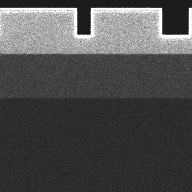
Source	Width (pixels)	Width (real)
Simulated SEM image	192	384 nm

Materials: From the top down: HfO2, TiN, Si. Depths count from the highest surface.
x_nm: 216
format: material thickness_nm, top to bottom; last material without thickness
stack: HfO2 92, TiN 88, Si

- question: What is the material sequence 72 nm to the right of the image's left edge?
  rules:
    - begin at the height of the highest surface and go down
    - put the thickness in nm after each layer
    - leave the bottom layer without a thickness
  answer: HfO2 92, TiN 88, Si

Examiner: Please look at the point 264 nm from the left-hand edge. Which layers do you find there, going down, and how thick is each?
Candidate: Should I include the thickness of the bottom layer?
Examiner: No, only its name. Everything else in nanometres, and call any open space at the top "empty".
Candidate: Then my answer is HfO2 92, TiN 88, Si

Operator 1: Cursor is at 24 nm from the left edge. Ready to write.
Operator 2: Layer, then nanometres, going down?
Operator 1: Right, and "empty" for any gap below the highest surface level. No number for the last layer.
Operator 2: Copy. HfO2 92, TiN 88, Si